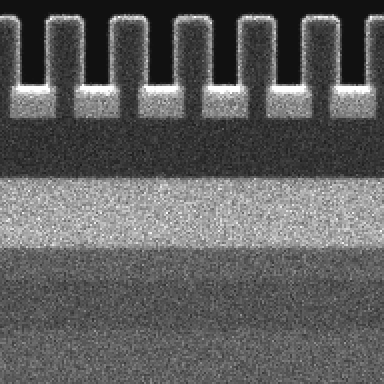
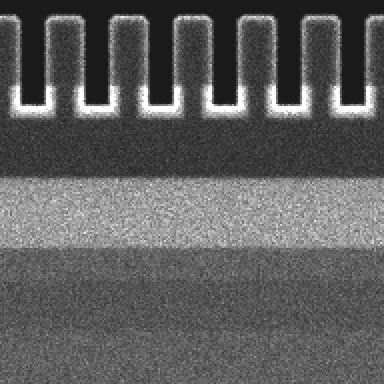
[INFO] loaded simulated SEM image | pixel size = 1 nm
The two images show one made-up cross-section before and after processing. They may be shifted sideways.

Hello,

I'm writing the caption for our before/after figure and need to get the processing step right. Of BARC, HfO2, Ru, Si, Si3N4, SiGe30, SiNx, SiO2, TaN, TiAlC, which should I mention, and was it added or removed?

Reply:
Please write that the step removed SiO2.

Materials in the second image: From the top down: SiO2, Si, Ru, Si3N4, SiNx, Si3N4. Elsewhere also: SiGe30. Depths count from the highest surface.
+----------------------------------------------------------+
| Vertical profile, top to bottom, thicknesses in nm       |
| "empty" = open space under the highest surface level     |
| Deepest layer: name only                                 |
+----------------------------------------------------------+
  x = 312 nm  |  SiGe30 10, Si 152, Ru 70, Si3N4 32, SiNx 50, Si3N4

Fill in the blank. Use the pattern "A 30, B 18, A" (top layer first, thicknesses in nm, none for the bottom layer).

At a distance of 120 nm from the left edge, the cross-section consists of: SiGe30 10, Si 152, Ru 70, Si3N4 32, SiNx 50, Si3N4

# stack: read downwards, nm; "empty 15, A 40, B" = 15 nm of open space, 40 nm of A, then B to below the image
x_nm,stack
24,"empty 90, SiO2 12, Si 60, Ru 70, Si3N4 32, SiNx 50, Si3N4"